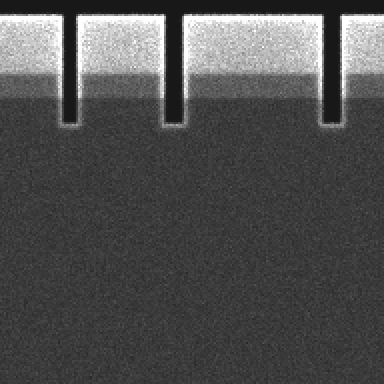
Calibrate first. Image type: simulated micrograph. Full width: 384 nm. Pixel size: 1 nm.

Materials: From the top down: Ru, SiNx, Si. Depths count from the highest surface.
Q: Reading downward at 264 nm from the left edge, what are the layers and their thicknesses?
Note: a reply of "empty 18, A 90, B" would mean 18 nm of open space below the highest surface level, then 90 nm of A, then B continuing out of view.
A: Ru 58, SiNx 24, Si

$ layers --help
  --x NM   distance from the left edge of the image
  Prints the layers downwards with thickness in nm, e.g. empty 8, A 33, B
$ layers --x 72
empty 108, Si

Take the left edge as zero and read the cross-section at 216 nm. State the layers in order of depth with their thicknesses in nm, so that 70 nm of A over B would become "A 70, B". Ru 58, SiNx 24, Si